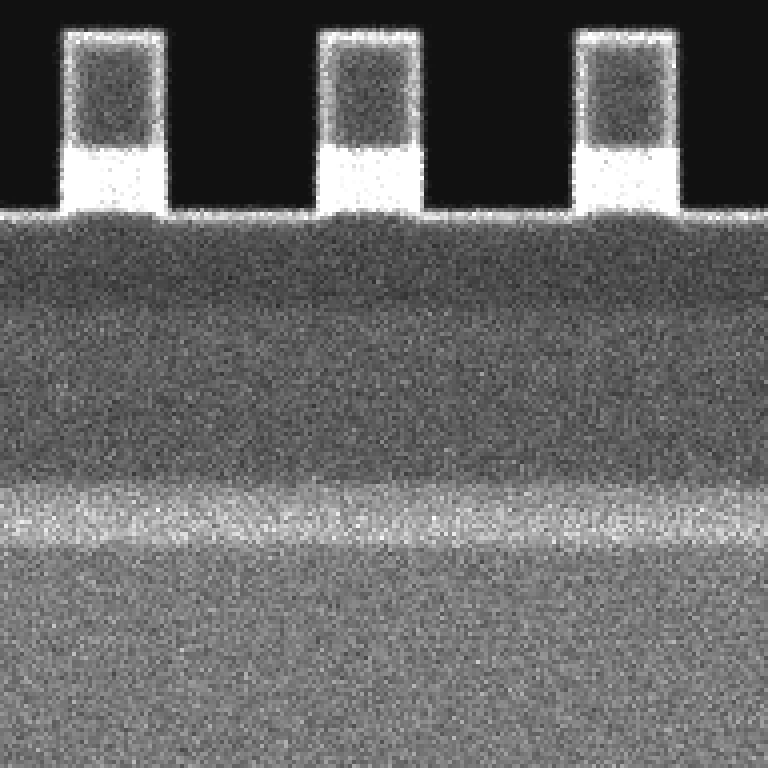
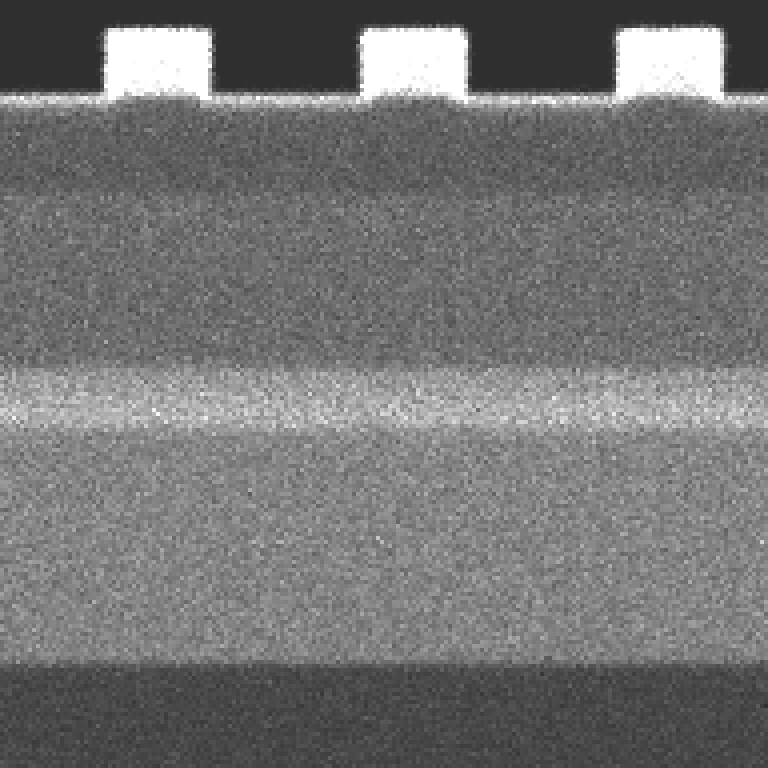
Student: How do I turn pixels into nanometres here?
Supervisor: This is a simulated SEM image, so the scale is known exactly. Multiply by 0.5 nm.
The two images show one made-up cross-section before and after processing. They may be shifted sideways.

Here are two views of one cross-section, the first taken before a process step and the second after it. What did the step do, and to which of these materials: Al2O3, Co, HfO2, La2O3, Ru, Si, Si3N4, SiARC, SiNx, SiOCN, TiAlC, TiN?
It removed SiARC.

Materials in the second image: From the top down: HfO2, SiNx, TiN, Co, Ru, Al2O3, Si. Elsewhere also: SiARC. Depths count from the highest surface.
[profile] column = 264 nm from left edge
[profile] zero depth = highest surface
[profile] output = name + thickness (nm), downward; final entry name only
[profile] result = empty 32, SiNx 48, TiN 88, Co 14, Ru 16, Al2O3 118, Si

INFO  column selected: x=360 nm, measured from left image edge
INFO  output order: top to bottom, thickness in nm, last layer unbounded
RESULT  empty 32, SiNx 48, TiN 88, Co 14, Ru 16, Al2O3 118, Si